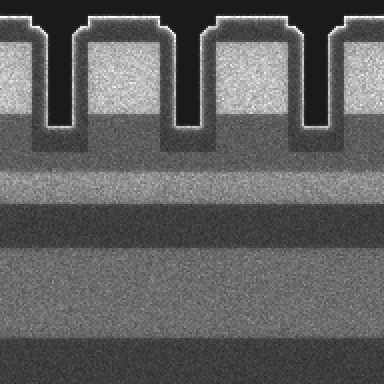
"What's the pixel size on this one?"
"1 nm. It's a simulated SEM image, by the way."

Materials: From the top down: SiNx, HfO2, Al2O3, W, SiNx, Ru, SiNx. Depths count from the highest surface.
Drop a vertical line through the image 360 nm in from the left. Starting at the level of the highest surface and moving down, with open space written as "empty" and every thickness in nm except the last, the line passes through SiNx 26, HfO2 72, Al2O3 58, W 32, SiNx 44, Ru 90, SiNx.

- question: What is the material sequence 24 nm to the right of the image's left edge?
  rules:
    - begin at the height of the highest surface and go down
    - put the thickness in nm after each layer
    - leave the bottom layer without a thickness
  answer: SiNx 26, HfO2 72, Al2O3 58, W 32, SiNx 44, Ru 90, SiNx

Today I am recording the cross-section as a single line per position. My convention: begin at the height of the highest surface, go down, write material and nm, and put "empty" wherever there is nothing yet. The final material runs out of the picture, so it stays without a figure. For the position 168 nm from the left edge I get empty 12, SiNx 124, Al2O3 20, W 32, SiNx 44, Ru 90, SiNx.